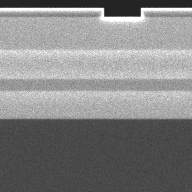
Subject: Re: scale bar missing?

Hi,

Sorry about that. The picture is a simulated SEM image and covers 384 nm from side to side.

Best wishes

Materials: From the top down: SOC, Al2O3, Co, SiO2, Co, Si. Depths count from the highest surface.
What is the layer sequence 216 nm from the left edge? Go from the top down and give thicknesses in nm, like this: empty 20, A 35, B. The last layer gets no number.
empty 18, Al2O3 66, Co 58, SiO2 24, Co 56, Si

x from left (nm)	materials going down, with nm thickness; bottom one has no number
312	SOC 18, Al2O3 66, Co 58, SiO2 24, Co 56, Si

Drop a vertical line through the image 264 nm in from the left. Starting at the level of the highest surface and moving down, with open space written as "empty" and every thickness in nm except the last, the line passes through empty 18, Al2O3 66, Co 58, SiO2 24, Co 56, Si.